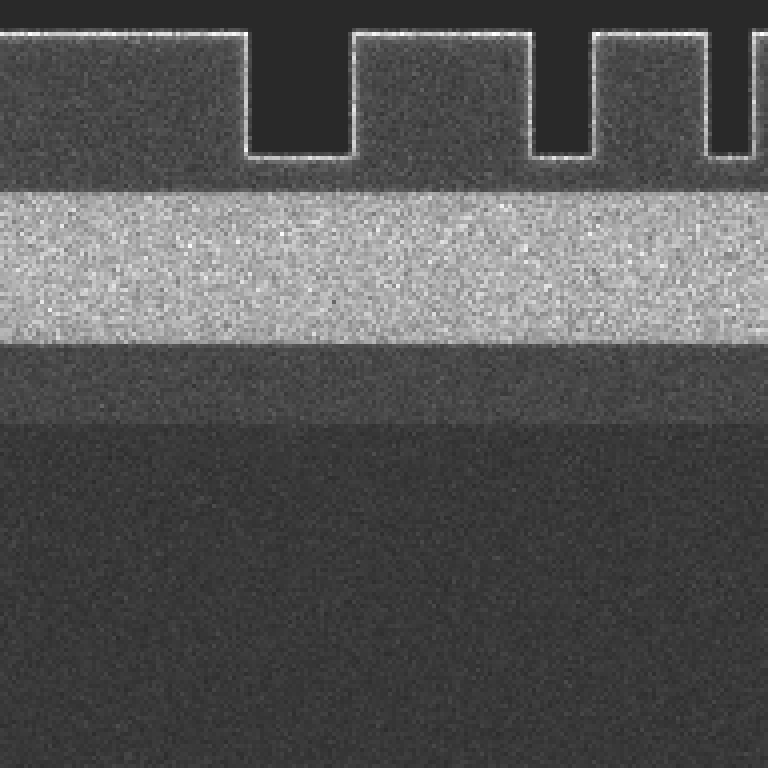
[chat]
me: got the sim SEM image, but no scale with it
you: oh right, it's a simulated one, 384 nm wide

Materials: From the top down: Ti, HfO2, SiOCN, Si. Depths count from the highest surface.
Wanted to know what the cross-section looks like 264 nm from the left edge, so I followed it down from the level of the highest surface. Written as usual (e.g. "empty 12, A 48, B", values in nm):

Ti 80, HfO2 76, SiOCN 40, Si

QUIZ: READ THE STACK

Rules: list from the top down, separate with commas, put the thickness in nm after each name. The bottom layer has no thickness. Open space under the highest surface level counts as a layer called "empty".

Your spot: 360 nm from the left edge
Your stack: empty 62, Ti 18, HfO2 76, SiOCN 40, Si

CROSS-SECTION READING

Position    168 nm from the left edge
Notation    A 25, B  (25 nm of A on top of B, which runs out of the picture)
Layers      empty 62, Ti 18, HfO2 76, SiOCN 40, Si